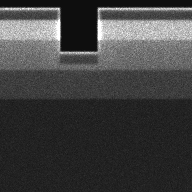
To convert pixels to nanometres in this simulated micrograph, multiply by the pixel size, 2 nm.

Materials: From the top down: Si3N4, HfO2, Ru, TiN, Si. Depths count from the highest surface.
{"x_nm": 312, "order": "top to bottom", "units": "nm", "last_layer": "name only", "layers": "Si3N4 24, HfO2 40, Ru 60, TiN 58, Si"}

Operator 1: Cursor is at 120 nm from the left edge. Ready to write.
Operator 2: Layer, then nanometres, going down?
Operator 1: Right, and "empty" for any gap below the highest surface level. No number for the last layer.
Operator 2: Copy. empty 88, Si3N4 24, Ru 12, TiN 58, Si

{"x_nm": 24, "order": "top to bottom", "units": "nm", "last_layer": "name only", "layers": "Si3N4 24, HfO2 40, Ru 60, TiN 58, Si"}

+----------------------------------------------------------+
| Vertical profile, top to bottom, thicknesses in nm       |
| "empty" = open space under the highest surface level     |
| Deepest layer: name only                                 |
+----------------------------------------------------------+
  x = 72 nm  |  Si3N4 24, HfO2 40, Ru 60, TiN 58, Si